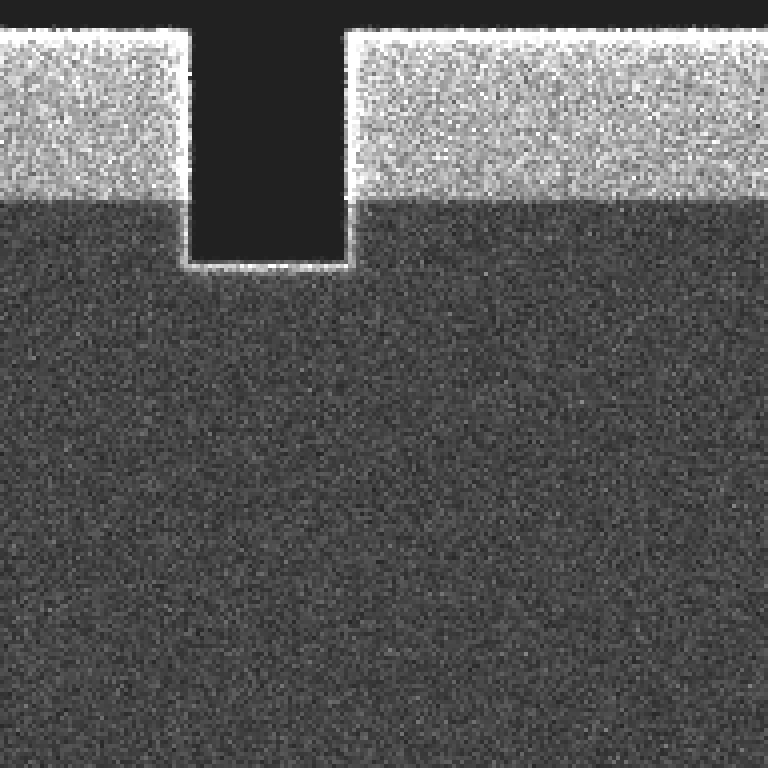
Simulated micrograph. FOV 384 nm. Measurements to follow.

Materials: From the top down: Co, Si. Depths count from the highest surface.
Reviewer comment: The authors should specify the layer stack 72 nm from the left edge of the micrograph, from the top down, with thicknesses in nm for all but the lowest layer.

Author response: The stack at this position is Co 84, Si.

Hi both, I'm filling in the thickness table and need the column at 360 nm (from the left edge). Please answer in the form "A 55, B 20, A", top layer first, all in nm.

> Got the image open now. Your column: Co 84, Si